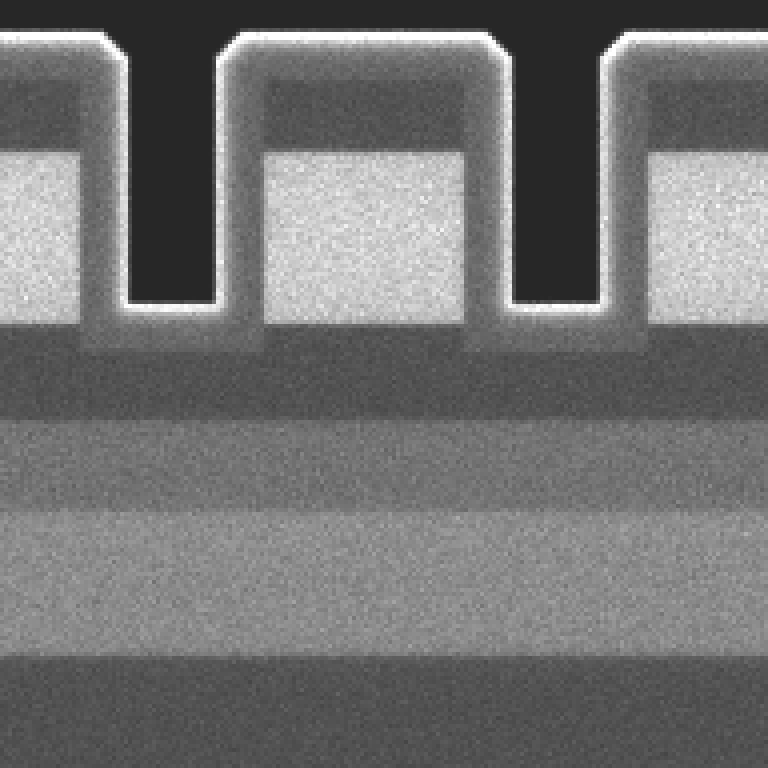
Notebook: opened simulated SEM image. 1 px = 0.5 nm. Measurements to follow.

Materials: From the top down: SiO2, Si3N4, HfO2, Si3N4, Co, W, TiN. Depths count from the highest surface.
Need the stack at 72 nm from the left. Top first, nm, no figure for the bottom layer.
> empty 136, SiO2 24, Si3N4 34, Co 46, W 72, TiN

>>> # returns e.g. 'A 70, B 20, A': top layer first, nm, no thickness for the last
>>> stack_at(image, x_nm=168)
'SiO2 24, Si3N4 36, HfO2 86, Si3N4 48, Co 46, W 72, TiN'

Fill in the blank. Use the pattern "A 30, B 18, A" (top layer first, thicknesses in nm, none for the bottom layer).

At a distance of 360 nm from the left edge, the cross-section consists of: SiO2 24, Si3N4 36, HfO2 86, Si3N4 48, Co 46, W 72, TiN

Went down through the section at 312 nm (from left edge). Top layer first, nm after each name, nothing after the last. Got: SiO2 160, Si3N4 34, Co 46, W 72, TiN